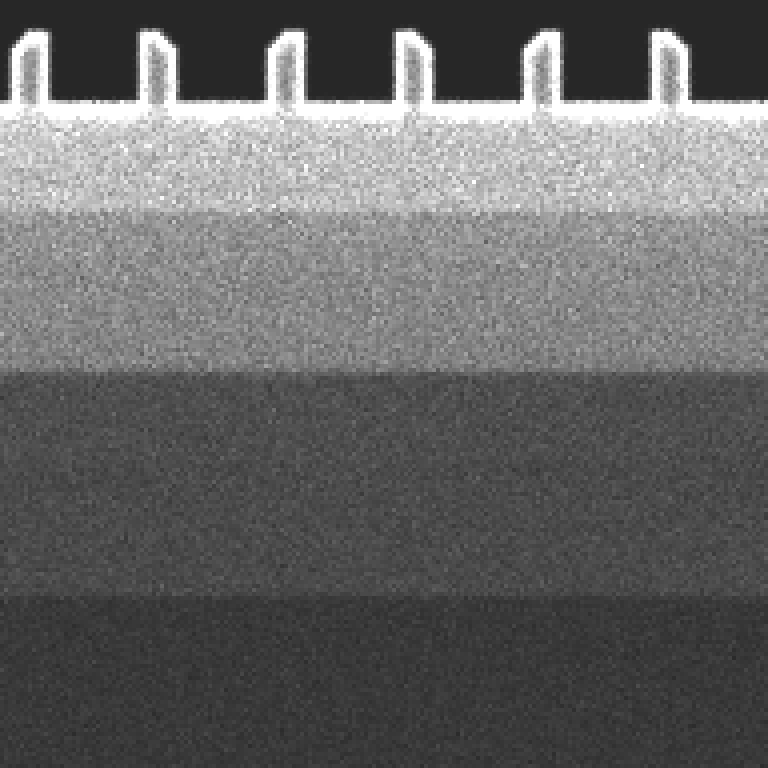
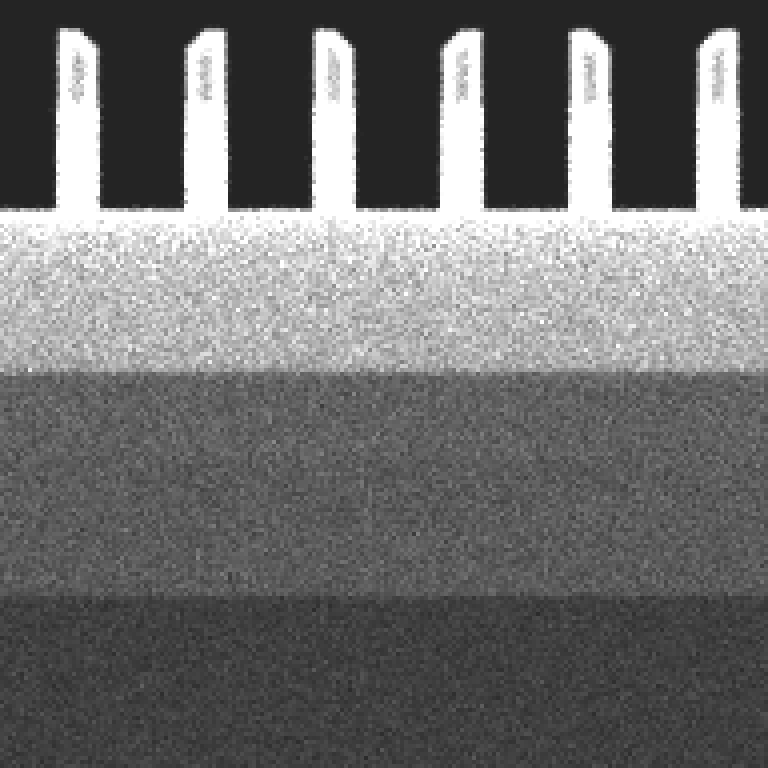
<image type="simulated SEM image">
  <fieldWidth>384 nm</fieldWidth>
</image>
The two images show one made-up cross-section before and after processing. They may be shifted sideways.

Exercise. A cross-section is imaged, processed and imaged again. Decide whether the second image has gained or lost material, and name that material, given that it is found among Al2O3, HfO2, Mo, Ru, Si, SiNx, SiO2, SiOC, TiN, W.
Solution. removed: HfO2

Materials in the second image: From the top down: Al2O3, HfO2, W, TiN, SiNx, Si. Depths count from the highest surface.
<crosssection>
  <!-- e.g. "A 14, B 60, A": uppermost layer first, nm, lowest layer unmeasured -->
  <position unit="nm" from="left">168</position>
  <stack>empty 2, Al2O3 34, HfO2 54, W 80, TiN 44, SiNx 68, Si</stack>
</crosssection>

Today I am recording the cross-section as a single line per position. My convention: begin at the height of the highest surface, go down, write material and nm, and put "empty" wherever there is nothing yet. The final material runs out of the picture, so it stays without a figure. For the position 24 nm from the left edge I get empty 90, W 80, TiN 44, SiNx 68, Si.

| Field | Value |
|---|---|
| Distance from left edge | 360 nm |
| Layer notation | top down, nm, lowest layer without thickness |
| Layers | Al2O3 36, HfO2 54, W 80, TiN 44, SiNx 68, Si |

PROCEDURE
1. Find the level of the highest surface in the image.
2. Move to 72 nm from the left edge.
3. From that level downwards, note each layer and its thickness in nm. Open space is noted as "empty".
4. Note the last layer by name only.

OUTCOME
empty 90, W 80, TiN 44, SiNx 68, Si